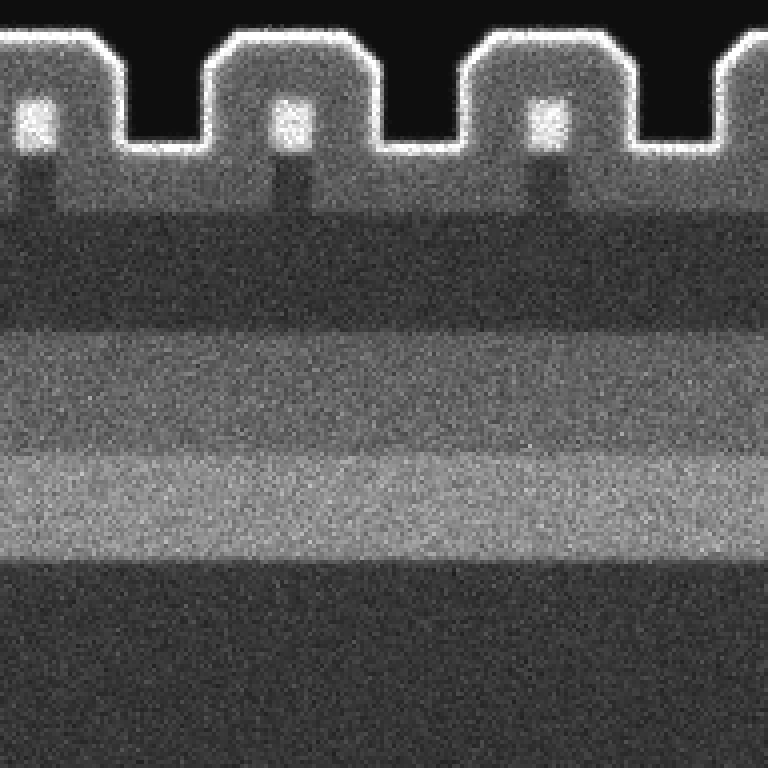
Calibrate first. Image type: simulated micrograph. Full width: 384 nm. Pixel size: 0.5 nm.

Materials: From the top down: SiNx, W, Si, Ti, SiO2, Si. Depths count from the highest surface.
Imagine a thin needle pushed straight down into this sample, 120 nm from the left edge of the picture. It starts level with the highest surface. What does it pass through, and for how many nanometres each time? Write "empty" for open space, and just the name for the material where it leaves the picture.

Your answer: SiNx 90, Si 60, Ti 62, SiO2 52, Si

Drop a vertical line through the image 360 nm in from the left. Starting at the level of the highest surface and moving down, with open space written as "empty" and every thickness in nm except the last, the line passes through empty 14, SiNx 76, Si 60, Ti 62, SiO2 52, Si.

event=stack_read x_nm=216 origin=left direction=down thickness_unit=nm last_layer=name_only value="empty 56, SiNx 34, Si 60, Ti 62, SiO2 52, Si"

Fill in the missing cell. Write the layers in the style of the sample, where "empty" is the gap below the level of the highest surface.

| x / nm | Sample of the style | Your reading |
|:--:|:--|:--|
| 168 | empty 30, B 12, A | SiNx 90, Si 60, Ti 62, SiO2 52, Si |